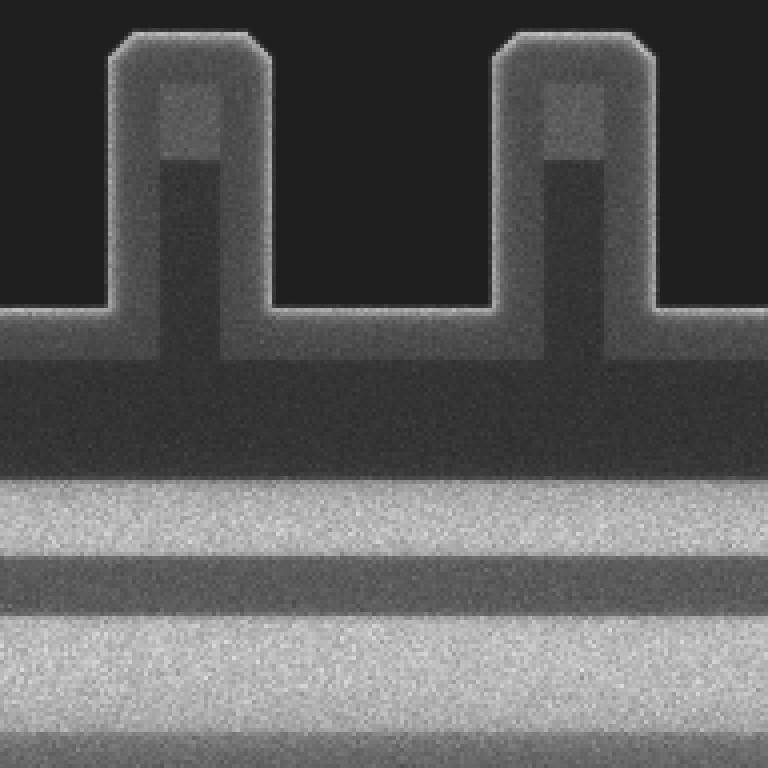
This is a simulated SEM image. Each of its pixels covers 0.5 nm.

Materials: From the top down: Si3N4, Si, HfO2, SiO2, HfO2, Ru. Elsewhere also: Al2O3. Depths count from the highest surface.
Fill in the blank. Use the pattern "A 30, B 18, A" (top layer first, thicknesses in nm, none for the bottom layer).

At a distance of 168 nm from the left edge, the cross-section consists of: empty 138, Si3N4 26, Si 60, HfO2 38, SiO2 30, HfO2 58, Ru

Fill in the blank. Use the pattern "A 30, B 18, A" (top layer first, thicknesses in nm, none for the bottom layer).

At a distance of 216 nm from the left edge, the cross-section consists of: empty 138, Si3N4 26, Si 60, HfO2 38, SiO2 30, HfO2 58, Ru